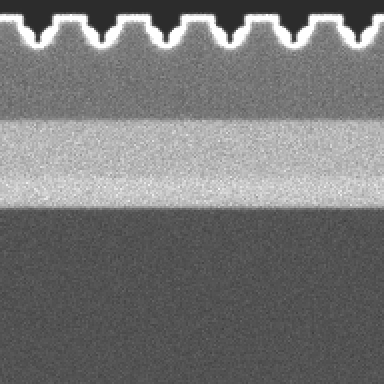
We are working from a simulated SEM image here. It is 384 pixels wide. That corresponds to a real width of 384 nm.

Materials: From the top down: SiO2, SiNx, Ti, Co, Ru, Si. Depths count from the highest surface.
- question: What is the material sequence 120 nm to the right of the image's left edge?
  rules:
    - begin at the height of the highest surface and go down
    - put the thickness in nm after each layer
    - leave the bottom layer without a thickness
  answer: SiNx 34, Ti 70, Co 58, Ru 30, Si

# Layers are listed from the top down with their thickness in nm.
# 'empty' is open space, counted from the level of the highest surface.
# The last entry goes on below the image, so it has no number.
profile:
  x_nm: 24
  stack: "empty 12, SiO2 16, SiNx 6, Ti 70, Co 58, Ru 30, Si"